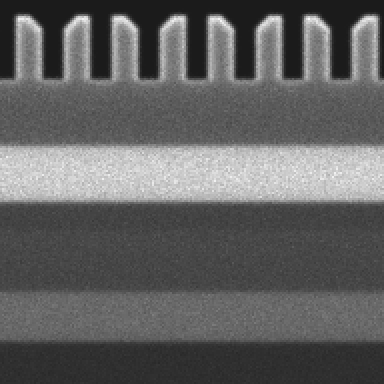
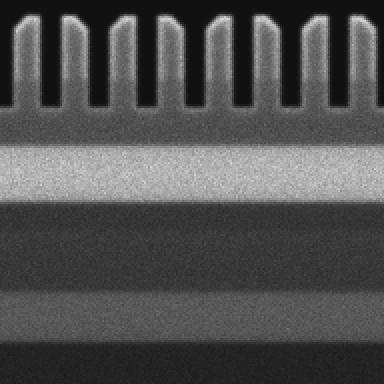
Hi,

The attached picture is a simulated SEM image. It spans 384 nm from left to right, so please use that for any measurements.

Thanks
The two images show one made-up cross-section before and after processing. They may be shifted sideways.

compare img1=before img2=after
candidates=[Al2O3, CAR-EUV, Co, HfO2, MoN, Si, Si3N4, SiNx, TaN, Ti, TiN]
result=removed:TiN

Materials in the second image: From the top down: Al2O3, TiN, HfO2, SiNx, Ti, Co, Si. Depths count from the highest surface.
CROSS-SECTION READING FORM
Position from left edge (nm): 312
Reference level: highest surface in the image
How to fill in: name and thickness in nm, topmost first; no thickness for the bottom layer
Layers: empty 2, Al2O3 62, TiN 66, HfO2 56, SiNx 28, Ti 62, Co 50, Si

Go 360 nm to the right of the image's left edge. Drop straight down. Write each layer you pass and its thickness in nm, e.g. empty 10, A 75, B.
Al2O3 64, TiN 66, HfO2 56, SiNx 28, Ti 62, Co 50, Si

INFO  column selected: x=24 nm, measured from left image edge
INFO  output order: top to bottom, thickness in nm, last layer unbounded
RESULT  empty 2, Al2O3 62, TiN 66, HfO2 56, SiNx 28, Ti 62, Co 50, Si